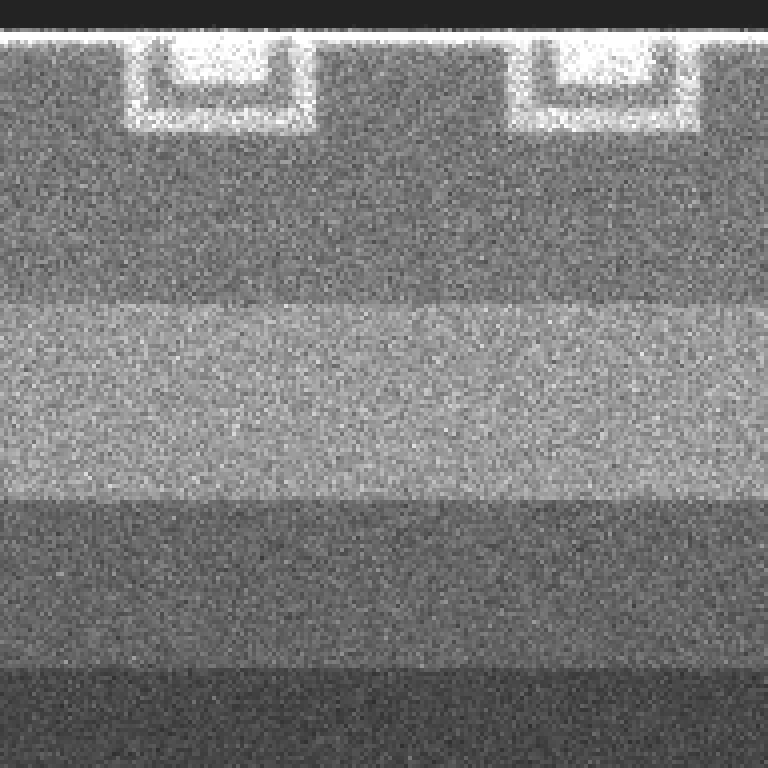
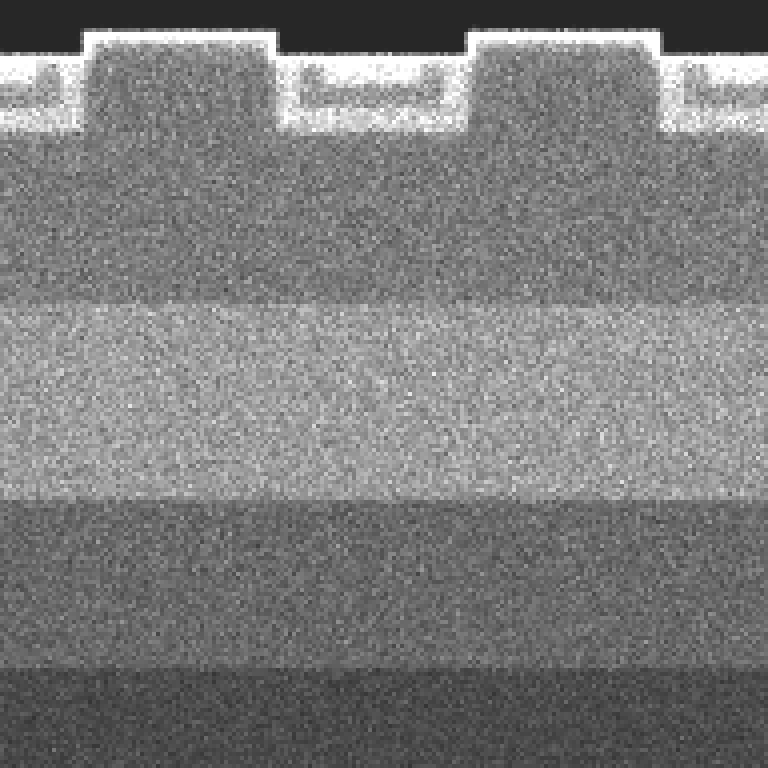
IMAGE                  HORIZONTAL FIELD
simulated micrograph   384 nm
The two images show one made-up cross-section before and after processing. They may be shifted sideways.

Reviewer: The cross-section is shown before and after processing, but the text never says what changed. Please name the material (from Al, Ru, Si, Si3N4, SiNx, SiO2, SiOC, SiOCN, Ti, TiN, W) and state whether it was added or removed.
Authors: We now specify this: Ru and TiN and W, removed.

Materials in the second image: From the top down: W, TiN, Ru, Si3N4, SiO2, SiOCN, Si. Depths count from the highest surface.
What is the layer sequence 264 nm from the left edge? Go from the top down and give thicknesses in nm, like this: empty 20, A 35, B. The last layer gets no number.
Si3N4 136, SiO2 98, SiOCN 84, Si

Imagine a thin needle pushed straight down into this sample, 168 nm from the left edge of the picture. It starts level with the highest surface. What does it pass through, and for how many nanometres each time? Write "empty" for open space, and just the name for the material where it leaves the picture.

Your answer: empty 12, W 14, TiN 12, Ru 12, Si3N4 86, SiO2 98, SiOCN 84, Si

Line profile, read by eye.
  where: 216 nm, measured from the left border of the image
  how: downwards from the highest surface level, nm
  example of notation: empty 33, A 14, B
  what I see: empty 12, TiN 26, Ru 12, Si3N4 86, SiO2 98, SiOCN 84, Si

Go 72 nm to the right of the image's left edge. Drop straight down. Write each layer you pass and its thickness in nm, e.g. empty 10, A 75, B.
Si3N4 136, SiO2 98, SiOCN 84, Si